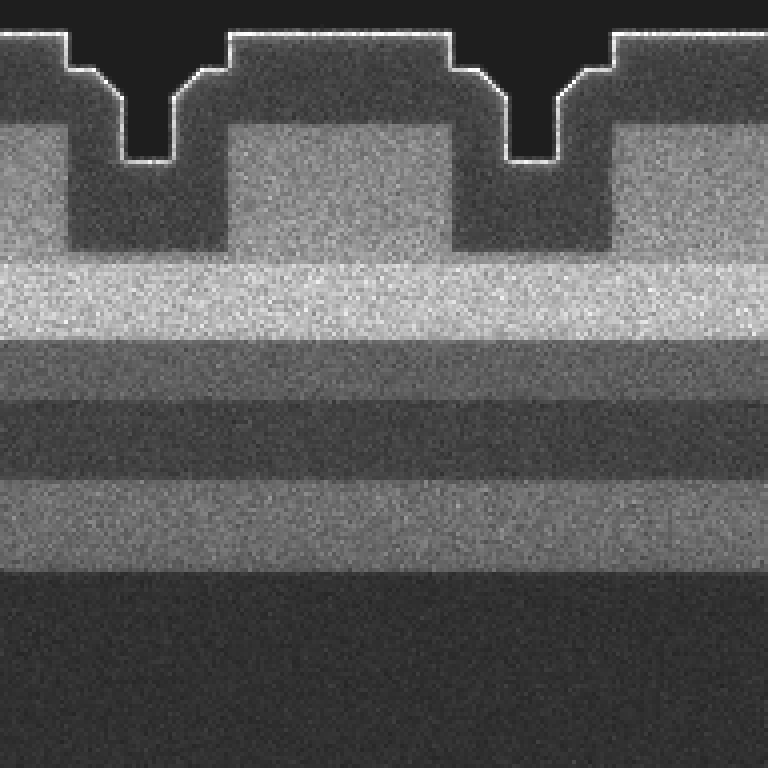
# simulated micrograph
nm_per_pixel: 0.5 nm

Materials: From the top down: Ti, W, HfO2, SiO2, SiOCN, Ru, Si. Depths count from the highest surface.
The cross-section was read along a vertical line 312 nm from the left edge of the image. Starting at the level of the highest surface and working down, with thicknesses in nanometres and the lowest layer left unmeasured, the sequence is Ti 46, W 70, HfO2 38, SiO2 30, SiOCN 40, Ru 46, Si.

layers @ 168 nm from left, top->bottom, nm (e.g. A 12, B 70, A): Ti 46, W 70, HfO2 38, SiO2 30, SiOCN 40, Ru 46, Si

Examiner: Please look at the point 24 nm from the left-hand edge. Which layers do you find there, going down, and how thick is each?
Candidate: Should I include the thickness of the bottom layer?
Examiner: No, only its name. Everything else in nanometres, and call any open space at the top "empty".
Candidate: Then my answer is Ti 46, W 70, HfO2 38, SiO2 30, SiOCN 40, Ru 46, Si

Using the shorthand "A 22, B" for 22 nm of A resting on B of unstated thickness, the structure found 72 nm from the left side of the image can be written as empty 64, Ti 46, W 6, HfO2 38, SiO2 30, SiOCN 40, Ru 46, Si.